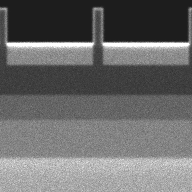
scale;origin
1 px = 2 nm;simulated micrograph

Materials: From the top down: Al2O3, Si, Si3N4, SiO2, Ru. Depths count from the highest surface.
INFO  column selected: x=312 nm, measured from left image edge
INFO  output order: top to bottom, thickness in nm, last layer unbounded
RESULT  empty 70, Al2O3 44, Si 60, Si3N4 50, SiO2 76, Ru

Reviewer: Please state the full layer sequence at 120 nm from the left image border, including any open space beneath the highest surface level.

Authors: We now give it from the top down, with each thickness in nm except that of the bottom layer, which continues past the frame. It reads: empty 70, Al2O3 44, Si 60, Si3N4 50, SiO2 76, Ru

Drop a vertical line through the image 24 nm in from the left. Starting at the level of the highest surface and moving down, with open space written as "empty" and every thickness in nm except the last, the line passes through empty 70, Al2O3 44, Si 60, Si3N4 50, SiO2 76, Ru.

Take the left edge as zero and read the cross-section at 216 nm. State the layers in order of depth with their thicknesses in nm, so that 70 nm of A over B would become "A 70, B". empty 70, Al2O3 44, Si 60, Si3N4 50, SiO2 76, Ru